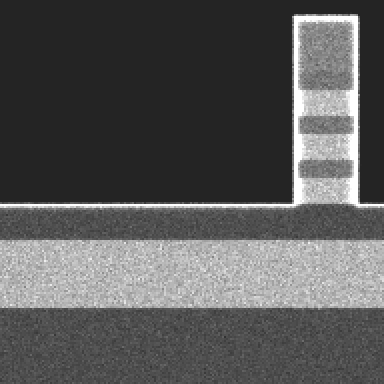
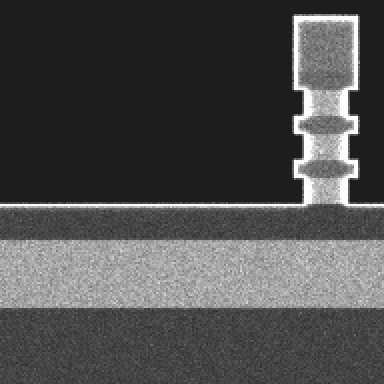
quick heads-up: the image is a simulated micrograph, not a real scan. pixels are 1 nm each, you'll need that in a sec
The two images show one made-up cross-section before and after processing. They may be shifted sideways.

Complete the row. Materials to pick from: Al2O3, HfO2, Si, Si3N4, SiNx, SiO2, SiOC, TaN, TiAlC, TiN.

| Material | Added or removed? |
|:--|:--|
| Al2O3 | removed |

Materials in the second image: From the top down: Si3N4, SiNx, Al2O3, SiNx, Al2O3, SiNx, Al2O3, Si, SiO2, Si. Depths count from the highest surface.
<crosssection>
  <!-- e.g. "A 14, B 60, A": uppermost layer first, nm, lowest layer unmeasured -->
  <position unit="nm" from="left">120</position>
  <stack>empty 188, Si 36, SiO2 68, Si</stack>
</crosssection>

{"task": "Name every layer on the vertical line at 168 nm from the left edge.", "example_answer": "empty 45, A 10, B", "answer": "empty 188, Si 36, SiO2 68, Si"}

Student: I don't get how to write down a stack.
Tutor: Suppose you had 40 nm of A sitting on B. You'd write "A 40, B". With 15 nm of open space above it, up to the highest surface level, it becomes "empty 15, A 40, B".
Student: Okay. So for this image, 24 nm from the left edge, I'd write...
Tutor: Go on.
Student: empty 188, Si 36, SiO2 68, Si